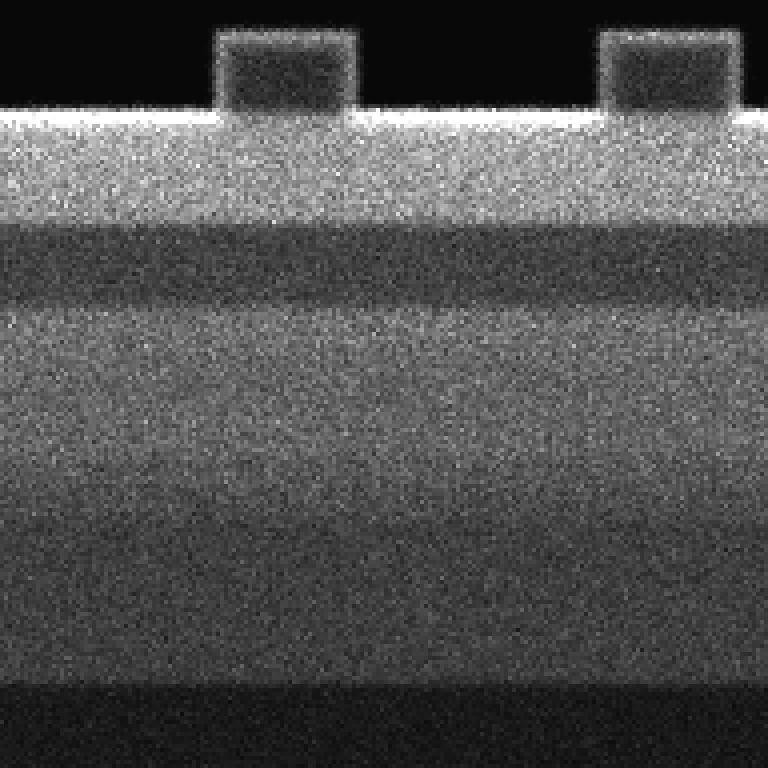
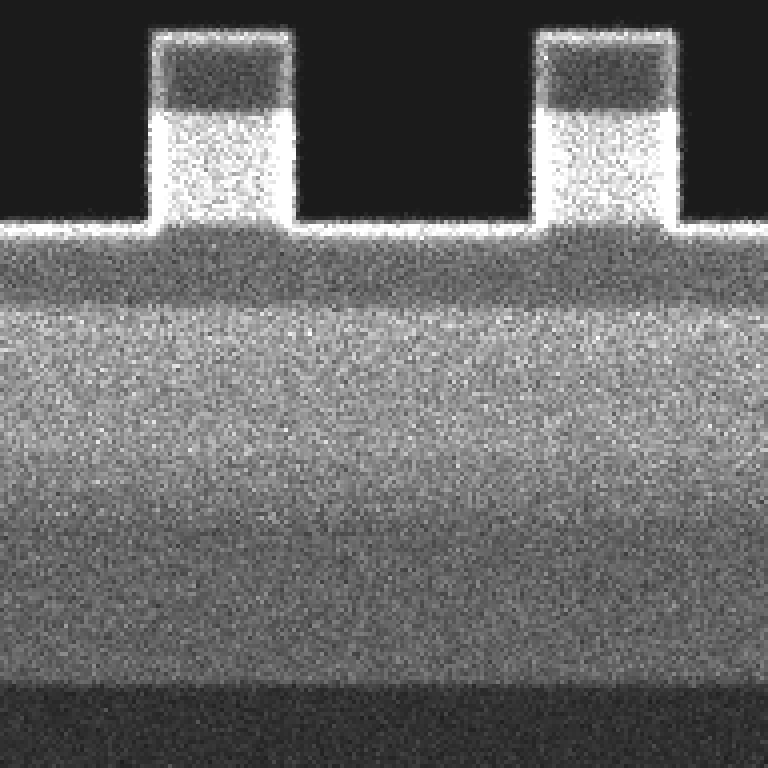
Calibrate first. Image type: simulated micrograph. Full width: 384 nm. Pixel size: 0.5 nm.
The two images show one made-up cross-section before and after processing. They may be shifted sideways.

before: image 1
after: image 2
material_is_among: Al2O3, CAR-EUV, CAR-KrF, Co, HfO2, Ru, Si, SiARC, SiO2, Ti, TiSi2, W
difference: HfO2, removed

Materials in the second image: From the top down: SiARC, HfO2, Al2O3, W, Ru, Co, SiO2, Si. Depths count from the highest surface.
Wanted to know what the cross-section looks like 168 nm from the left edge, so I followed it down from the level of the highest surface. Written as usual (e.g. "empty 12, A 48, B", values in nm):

empty 96, Al2O3 42, W 74, Ru 16, Co 16, SiO2 82, Si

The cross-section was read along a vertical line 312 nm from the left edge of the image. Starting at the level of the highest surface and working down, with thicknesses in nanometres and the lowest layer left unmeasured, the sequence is SiARC 40, HfO2 56, Al2O3 42, W 74, Ru 16, Co 16, SiO2 82, Si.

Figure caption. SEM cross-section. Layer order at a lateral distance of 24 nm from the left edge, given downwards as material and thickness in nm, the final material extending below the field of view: empty 96, Al2O3 42, W 74, Ru 16, Co 16, SiO2 82, Si